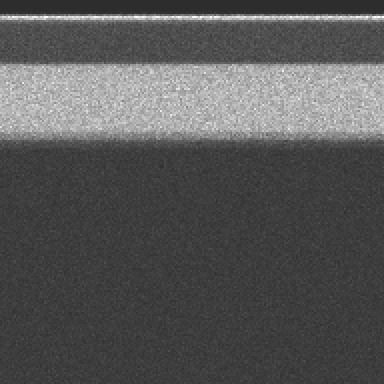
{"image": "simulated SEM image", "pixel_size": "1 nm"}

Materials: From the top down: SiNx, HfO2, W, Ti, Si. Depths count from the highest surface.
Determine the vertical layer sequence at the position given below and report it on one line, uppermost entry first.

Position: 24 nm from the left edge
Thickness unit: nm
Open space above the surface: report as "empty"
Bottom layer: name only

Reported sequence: SiNx 48, HfO2 68, W 8, Ti 8, Si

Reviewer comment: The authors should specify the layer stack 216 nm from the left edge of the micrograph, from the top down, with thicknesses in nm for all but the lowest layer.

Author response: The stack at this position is SiNx 48, HfO2 68, W 8, Ti 8, Si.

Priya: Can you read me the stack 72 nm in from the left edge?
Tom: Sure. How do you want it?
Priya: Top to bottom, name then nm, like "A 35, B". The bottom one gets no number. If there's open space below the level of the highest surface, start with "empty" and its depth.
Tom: SiNx 48, HfO2 68, W 8, Ti 8, Si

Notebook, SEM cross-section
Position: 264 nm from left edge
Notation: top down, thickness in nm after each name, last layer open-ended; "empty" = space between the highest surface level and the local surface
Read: SiNx 48, HfO2 68, W 8, Ti 8, Si